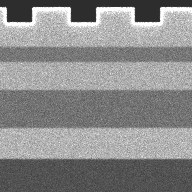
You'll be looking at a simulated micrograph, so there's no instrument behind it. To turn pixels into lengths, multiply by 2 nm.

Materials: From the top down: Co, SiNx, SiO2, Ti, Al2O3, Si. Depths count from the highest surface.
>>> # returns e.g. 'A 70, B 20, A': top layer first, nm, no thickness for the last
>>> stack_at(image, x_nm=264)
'Co 78, SiNx 30, SiO2 56, Ti 76, Al2O3 62, Si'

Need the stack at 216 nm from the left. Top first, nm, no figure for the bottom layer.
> Co 78, SiNx 30, SiO2 56, Ti 76, Al2O3 62, Si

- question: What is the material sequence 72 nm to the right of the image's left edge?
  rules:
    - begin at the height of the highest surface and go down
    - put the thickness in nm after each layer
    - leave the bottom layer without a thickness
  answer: Co 78, SiNx 30, SiO2 56, Ti 76, Al2O3 62, Si